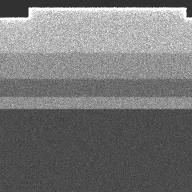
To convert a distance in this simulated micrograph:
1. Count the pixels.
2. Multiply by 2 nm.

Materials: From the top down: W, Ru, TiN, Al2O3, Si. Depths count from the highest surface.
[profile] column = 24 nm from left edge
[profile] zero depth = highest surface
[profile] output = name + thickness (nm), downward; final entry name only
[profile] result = empty 20, W 70, Ru 52, TiN 36, Al2O3 24, Si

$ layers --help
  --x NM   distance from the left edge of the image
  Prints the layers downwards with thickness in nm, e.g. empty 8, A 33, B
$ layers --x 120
W 90, Ru 52, TiN 36, Al2O3 24, Si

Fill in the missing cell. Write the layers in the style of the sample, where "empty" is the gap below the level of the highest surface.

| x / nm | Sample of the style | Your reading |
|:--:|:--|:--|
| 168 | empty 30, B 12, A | W 90, Ru 52, TiN 36, Al2O3 24, Si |